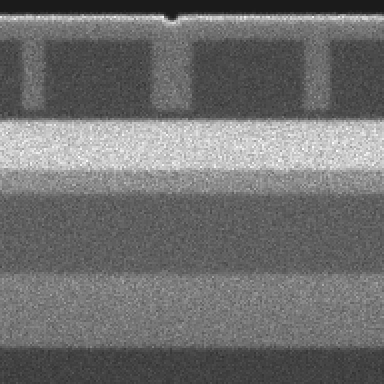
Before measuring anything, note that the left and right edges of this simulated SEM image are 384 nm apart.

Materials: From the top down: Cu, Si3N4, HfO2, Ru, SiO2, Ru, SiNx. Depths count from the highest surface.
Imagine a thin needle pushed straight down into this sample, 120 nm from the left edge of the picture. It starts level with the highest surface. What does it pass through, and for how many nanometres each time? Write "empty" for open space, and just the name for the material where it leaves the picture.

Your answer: Cu 24, Si3N4 80, HfO2 50, Ru 24, SiO2 80, Ru 74, SiNx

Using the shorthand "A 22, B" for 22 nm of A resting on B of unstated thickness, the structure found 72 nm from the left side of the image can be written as Cu 24, Si3N4 80, HfO2 50, Ru 24, SiO2 80, Ru 74, SiNx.